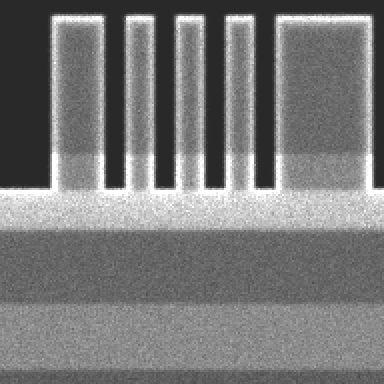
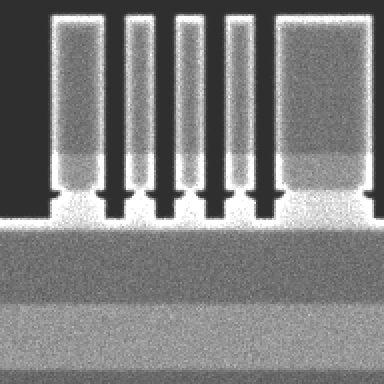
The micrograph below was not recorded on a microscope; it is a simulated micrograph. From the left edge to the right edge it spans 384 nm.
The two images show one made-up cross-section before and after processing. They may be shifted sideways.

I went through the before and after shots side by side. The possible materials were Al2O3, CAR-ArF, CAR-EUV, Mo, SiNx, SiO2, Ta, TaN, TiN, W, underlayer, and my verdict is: removed, W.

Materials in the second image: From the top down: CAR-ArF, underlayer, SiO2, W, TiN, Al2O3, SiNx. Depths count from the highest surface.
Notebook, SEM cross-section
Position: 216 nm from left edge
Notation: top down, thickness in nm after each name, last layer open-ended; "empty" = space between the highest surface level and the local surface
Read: empty 204, W 10, TiN 74, Al2O3 66, SiNx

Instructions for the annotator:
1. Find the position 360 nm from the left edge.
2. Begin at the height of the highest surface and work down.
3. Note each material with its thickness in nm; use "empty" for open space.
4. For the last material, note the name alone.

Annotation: CAR-ArF 80, underlayer 58, SiO2 36, W 40, TiN 74, Al2O3 66, SiNx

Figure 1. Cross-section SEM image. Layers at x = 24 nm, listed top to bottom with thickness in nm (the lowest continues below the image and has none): empty 204, W 10, TiN 74, Al2O3 66, SiNx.